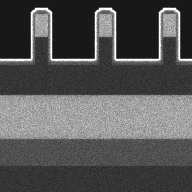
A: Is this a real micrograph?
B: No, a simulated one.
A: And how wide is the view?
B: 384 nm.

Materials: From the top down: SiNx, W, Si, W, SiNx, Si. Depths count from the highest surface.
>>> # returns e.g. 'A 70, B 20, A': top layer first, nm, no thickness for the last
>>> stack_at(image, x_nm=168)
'empty 102, SiNx 12, Si 60, W 88, SiNx 54, Si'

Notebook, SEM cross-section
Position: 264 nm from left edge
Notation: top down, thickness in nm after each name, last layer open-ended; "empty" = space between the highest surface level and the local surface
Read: empty 102, SiNx 12, Si 60, W 88, SiNx 54, Si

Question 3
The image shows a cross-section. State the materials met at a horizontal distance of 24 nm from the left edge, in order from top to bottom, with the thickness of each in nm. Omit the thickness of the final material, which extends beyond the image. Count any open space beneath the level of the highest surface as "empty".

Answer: empty 102, SiNx 12, Si 60, W 88, SiNx 54, Si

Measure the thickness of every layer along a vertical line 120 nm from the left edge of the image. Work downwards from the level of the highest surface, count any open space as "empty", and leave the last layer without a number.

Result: empty 102, SiNx 12, Si 60, W 88, SiNx 54, Si